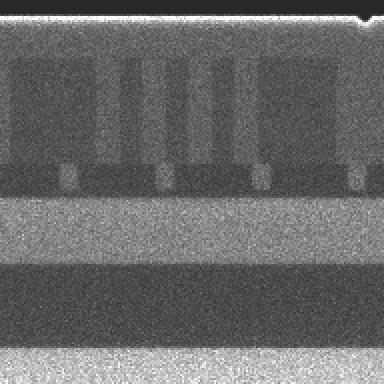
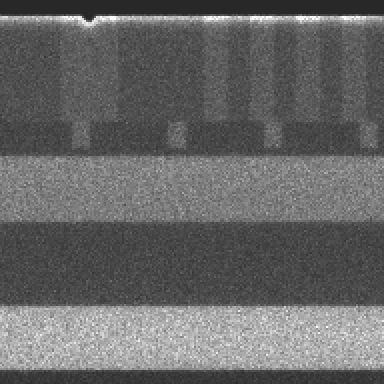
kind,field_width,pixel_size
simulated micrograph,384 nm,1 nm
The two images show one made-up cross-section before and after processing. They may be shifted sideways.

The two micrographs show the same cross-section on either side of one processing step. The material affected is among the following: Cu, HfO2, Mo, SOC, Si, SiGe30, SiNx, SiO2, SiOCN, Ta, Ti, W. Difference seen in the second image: SiO2 removed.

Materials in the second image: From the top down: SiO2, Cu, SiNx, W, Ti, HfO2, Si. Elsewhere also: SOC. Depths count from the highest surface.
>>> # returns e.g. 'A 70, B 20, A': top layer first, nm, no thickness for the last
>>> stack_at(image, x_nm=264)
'SiO2 106, Cu 26, SiNx 8, W 66, Ti 84, HfO2 64, Si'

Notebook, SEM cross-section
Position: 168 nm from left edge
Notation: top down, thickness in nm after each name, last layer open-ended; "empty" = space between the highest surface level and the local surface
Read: SOC 106, Cu 26, SiNx 8, W 66, Ti 84, HfO2 64, Si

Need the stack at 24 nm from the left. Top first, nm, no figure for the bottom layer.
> SOC 106, SiNx 34, W 66, Ti 84, HfO2 64, Si